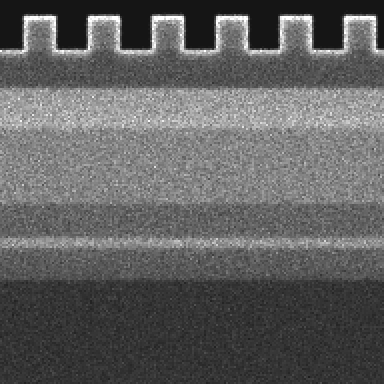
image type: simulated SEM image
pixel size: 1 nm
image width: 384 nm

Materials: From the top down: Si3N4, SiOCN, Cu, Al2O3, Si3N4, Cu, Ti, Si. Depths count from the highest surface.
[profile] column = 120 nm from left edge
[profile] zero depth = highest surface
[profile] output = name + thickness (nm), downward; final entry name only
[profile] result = empty 34, SiOCN 38, Cu 40, Al2O3 76, Si3N4 34, Cu 10, Ti 32, Si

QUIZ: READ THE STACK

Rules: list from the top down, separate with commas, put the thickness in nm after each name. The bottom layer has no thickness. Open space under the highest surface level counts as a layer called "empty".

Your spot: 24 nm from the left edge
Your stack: Si3N4 34, SiOCN 38, Cu 40, Al2O3 76, Si3N4 34, Cu 10, Ti 32, Si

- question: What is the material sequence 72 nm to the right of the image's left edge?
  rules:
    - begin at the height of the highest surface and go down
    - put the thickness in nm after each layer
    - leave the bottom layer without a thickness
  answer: empty 34, SiOCN 38, Cu 40, Al2O3 76, Si3N4 34, Cu 10, Ti 32, Si